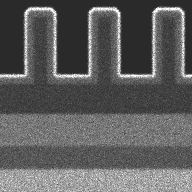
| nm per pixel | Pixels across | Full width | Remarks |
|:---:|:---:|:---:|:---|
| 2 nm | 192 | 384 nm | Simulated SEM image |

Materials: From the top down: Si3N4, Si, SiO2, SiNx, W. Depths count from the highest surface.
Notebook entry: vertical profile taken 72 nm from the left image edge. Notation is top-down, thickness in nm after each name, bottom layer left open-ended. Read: Si3N4 18, Si 194, SiO2 64, SiNx 46, W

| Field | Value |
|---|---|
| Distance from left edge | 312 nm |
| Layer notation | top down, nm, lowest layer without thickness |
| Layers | empty 2, Si3N4 150, Si 60, SiO2 64, SiNx 46, W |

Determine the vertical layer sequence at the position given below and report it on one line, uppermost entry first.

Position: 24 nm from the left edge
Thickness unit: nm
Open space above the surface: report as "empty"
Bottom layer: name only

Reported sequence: empty 134, Si3N4 18, Si 60, SiO2 64, SiNx 46, W